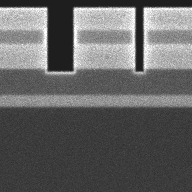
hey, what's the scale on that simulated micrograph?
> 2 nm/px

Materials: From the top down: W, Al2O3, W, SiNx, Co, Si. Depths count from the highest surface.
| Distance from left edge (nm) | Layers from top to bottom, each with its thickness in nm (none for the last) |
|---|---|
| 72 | W 44, Al2O3 28, W 50, SiNx 52, Co 24, Si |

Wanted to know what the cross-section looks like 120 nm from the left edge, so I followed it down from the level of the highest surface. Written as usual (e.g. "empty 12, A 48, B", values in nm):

empty 128, SiNx 46, Co 24, Si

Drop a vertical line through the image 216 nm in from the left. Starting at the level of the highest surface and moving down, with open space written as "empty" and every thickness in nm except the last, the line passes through W 44, Al2O3 28, W 50, SiNx 52, Co 24, Si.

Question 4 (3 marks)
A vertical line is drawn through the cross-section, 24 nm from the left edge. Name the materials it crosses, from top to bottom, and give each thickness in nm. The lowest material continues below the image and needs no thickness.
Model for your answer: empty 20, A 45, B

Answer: W 44, Al2O3 28, W 50, SiNx 52, Co 24, Si